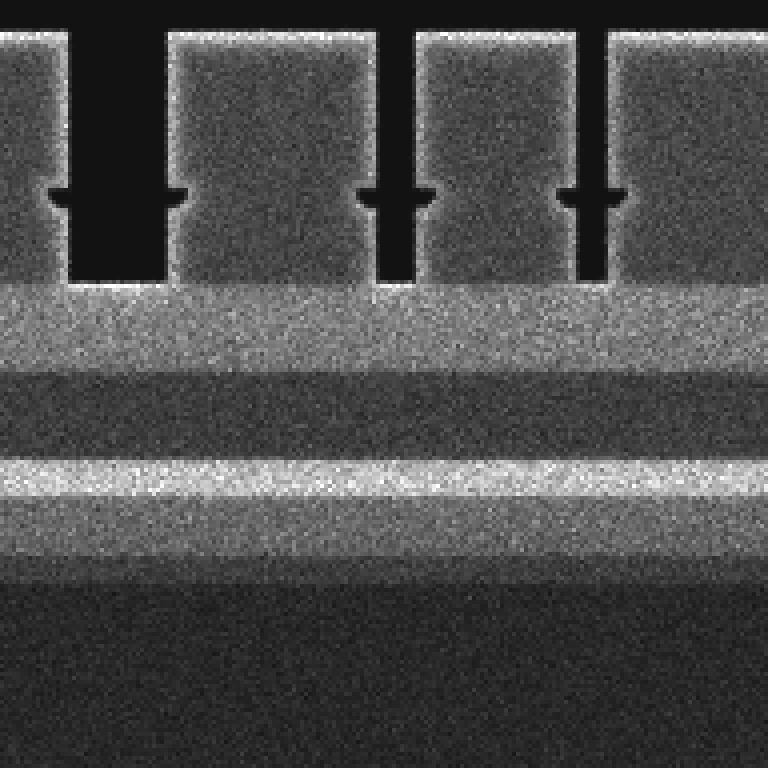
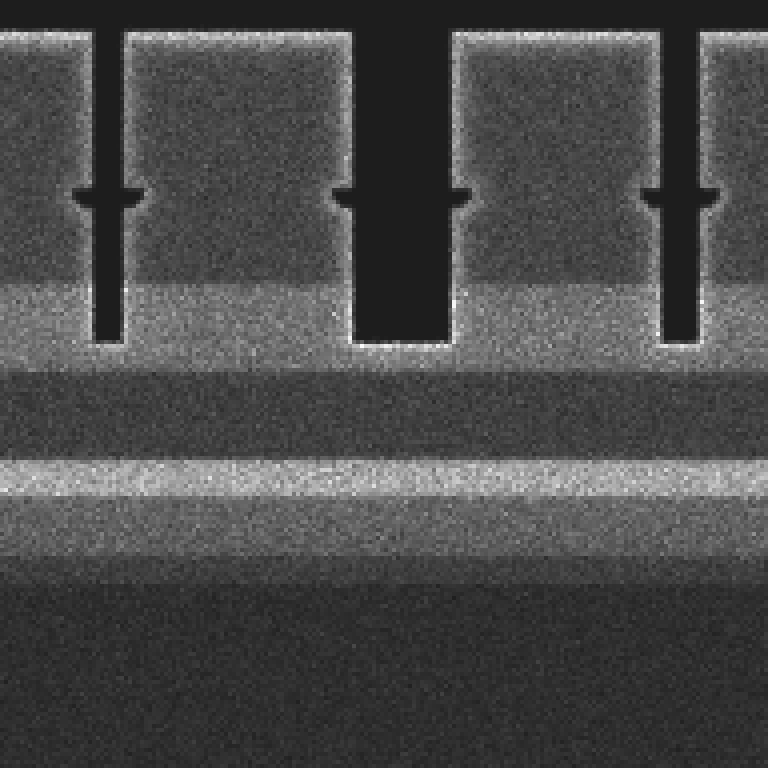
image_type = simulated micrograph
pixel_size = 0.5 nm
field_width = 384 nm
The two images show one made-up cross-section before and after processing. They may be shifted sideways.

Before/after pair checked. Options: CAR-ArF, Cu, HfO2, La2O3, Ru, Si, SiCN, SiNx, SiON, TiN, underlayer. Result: removed Ru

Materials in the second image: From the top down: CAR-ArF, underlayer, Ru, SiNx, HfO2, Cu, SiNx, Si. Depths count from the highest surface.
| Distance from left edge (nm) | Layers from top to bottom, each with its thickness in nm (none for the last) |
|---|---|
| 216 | empty 156, Ru 14, SiNx 44, HfO2 18, Cu 30, SiNx 14, Si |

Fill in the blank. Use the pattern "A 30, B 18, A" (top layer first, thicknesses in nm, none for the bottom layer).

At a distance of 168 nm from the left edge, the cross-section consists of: CAR-ArF 78, empty 8, underlayer 40, Ru 44, SiNx 44, HfO2 18, Cu 30, SiNx 14, Si